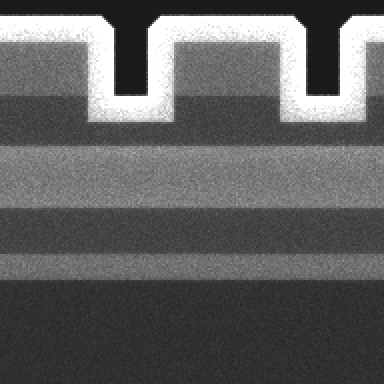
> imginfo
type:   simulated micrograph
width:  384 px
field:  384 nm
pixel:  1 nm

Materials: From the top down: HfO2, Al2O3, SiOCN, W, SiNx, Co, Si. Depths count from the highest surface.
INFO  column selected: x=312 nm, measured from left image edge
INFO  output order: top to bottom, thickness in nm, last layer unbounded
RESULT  empty 80, HfO2 26, SiOCN 24, W 62, SiNx 46, Co 26, Si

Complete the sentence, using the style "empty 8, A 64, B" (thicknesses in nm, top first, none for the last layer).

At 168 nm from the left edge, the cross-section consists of HfO2 106, SiOCN 24, W 62, SiNx 46, Co 26, Si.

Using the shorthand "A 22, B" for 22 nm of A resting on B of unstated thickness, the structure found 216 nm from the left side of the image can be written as HfO2 26, Al2O3 54, SiOCN 50, W 62, SiNx 46, Co 26, Si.